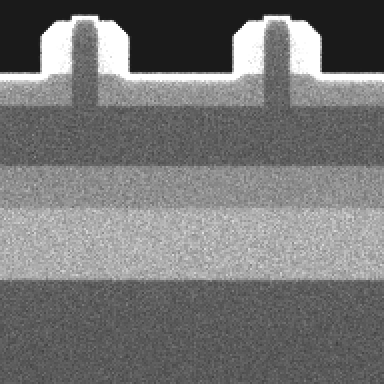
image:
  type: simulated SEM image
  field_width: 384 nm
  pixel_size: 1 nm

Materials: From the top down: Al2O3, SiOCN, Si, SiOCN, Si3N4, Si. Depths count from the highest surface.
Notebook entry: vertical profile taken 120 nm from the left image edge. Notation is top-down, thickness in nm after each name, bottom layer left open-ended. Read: empty 14, Al2O3 44, SiOCN 32, Si 60, SiOCN 42, Si3N4 72, Si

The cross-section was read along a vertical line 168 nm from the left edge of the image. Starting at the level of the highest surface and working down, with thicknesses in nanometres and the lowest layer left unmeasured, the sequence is empty 58, SiOCN 32, Si 60, SiOCN 42, Si3N4 72, Si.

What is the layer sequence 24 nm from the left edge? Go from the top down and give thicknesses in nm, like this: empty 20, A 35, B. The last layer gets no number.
empty 58, SiOCN 32, Si 60, SiOCN 42, Si3N4 72, Si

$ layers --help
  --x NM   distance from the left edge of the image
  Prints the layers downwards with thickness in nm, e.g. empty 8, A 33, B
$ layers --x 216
empty 58, SiOCN 32, Si 60, SiOCN 42, Si3N4 72, Si